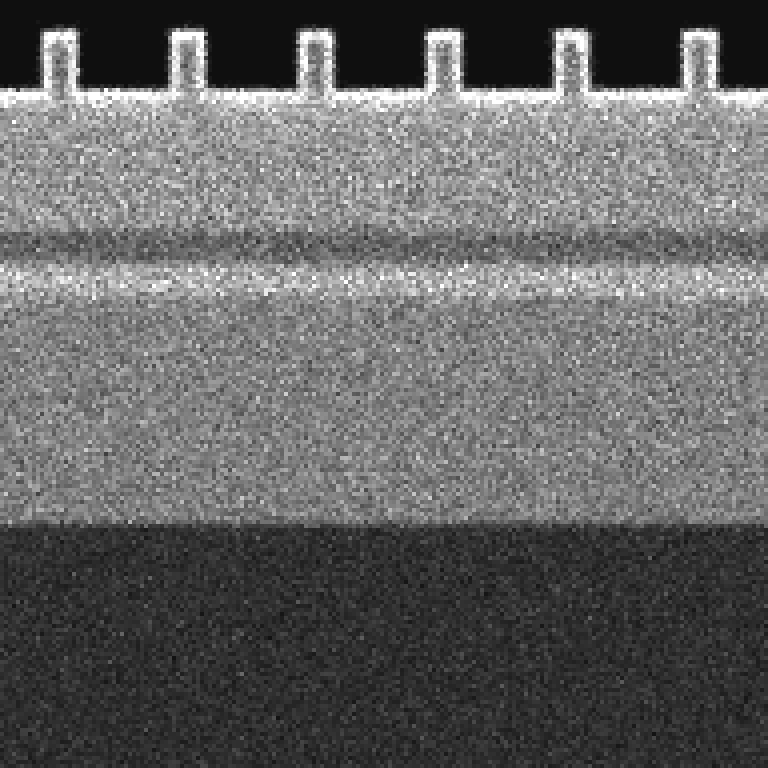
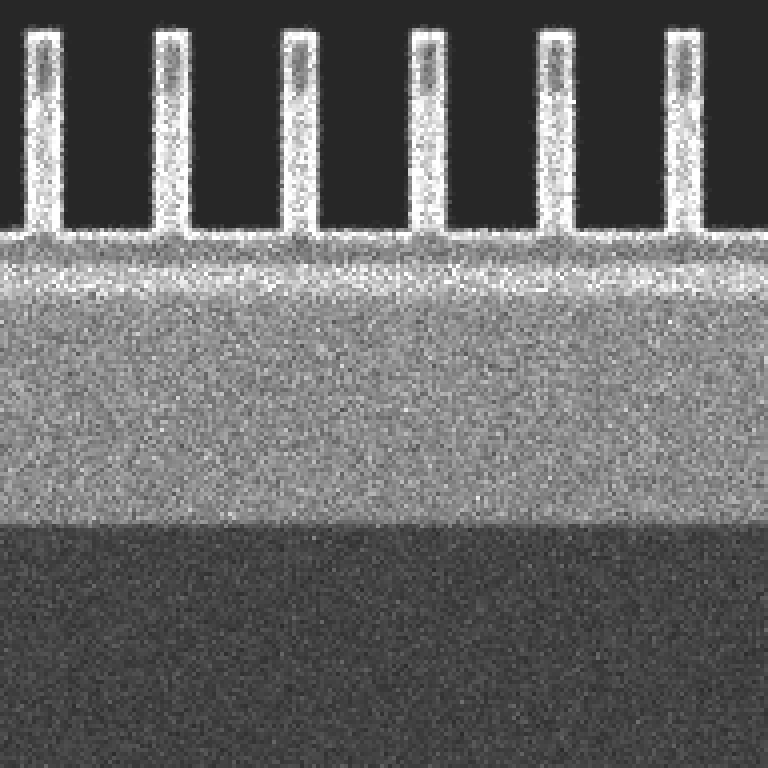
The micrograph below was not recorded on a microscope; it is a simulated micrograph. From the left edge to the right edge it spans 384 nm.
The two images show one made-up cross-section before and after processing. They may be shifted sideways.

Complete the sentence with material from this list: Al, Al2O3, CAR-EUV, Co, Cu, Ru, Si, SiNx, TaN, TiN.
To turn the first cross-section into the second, Co must be removed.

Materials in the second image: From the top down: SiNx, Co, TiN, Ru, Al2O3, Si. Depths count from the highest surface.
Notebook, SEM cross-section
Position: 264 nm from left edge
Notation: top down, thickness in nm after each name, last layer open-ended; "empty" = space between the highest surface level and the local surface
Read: empty 100, TiN 16, Ru 16, Al2O3 114, Si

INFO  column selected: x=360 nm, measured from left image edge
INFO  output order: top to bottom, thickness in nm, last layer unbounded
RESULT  empty 100, TiN 16, Ru 16, Al2O3 114, Si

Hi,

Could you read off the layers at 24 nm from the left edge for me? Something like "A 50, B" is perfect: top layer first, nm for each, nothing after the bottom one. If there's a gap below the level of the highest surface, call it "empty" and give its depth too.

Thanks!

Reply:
SiNx 30, Co 70, TiN 16, Ru 16, Al2O3 114, Si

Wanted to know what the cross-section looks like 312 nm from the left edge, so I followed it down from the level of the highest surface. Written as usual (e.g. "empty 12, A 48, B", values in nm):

empty 100, TiN 16, Ru 16, Al2O3 114, Si